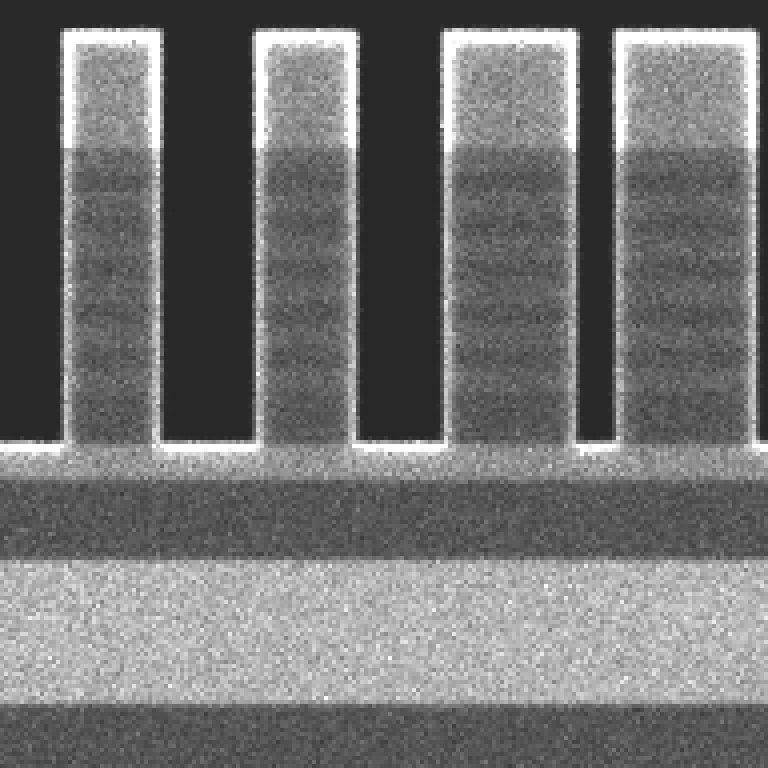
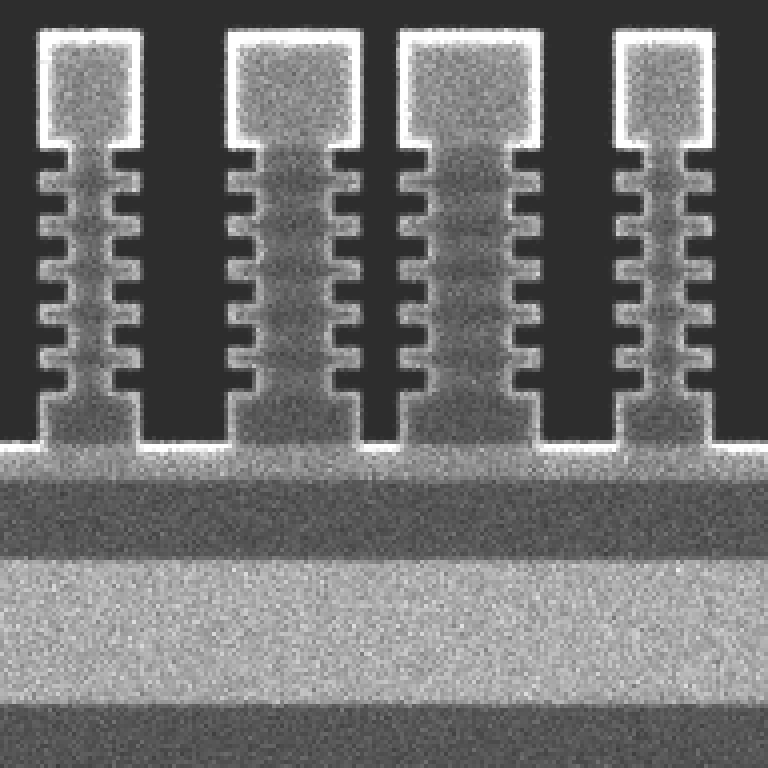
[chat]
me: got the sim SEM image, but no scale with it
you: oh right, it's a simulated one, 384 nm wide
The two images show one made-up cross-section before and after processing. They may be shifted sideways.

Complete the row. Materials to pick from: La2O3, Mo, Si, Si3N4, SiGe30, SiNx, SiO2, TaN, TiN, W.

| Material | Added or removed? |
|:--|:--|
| SiGe30 | removed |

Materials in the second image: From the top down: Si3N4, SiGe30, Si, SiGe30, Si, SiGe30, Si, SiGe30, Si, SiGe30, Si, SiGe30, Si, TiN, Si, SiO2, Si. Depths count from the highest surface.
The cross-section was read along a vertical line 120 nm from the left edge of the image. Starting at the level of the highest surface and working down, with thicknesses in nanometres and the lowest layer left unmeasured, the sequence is Si3N4 58, empty 12, Si 10, empty 12, Si 10, empty 12, Si 10, empty 12, Si 10, empty 12, Si 10, empty 12, Si 26, TiN 18, Si 40, SiO2 72, Si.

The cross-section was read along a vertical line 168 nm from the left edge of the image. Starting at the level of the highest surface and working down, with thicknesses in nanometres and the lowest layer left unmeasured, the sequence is Si3N4 58, empty 12, Si 10, empty 12, Si 10, empty 12, Si 10, empty 12, Si 10, empty 12, Si 10, empty 12, Si 26, TiN 18, Si 40, SiO2 72, Si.